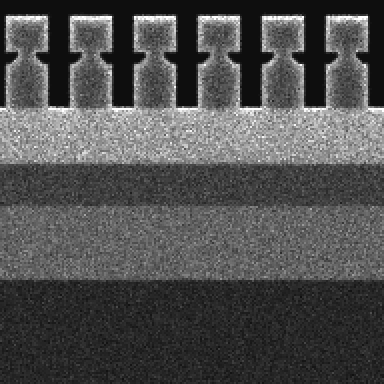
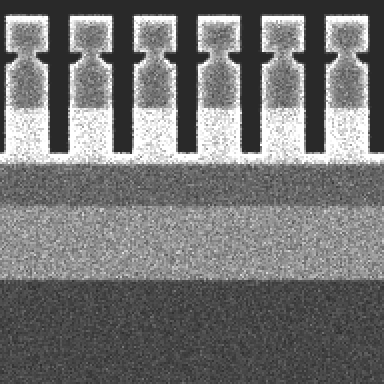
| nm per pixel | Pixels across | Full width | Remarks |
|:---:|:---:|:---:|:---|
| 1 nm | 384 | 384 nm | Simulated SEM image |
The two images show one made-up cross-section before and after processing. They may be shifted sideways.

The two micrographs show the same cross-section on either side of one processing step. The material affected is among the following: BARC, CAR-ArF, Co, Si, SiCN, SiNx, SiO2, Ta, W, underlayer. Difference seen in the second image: W removed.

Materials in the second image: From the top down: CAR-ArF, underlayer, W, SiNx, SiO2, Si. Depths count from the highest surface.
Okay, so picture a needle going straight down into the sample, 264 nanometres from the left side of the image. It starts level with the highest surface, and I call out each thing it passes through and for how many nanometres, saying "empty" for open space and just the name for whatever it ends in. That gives CAR-ArF 36, empty 12, underlayer 44, W 56, SiNx 42, SiO2 74, Si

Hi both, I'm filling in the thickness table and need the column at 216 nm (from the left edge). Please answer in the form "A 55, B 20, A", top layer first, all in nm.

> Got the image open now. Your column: CAR-ArF 36, underlayer 56, W 56, SiNx 42, SiO2 74, Si